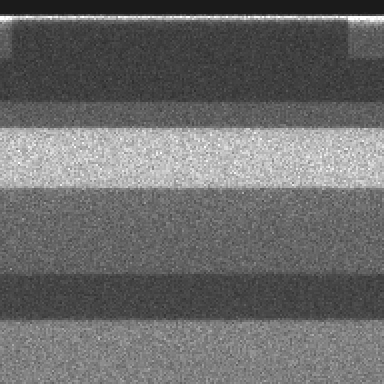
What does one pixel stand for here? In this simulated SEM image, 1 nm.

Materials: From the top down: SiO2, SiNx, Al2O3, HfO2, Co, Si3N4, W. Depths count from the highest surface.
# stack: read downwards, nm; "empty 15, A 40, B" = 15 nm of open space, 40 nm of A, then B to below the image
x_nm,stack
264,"SiNx 86, Al2O3 26, HfO2 60, Co 86, Si3N4 46, W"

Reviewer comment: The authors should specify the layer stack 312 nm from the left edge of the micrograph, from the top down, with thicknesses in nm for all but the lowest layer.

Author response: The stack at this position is SiNx 86, Al2O3 26, HfO2 60, Co 86, Si3N4 46, W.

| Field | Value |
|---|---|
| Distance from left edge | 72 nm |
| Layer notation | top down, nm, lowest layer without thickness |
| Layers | SiNx 86, Al2O3 26, HfO2 60, Co 86, Si3N4 46, W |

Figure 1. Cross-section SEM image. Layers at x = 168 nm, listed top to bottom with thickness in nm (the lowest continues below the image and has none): SiNx 86, Al2O3 26, HfO2 60, Co 86, Si3N4 46, W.